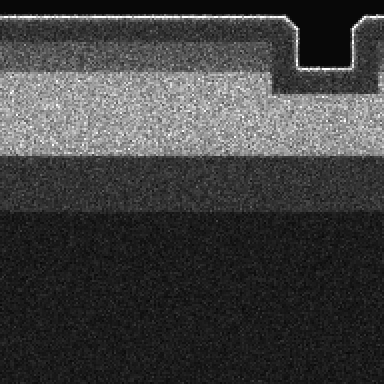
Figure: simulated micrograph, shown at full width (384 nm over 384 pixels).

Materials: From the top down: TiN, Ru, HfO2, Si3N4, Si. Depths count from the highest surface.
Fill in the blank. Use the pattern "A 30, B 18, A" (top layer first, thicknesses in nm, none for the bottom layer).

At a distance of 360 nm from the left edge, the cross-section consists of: empty 4, TiN 74, HfO2 62, Si3N4 56, Si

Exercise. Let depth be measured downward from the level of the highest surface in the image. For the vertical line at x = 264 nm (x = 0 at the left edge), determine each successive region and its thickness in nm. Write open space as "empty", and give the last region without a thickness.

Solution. TiN 26, Ru 30, HfO2 84, Si3N4 56, Si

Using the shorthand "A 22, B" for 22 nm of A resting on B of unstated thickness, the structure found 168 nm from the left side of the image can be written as TiN 26, Ru 30, HfO2 84, Si3N4 56, Si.